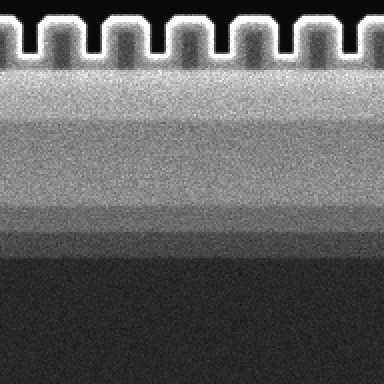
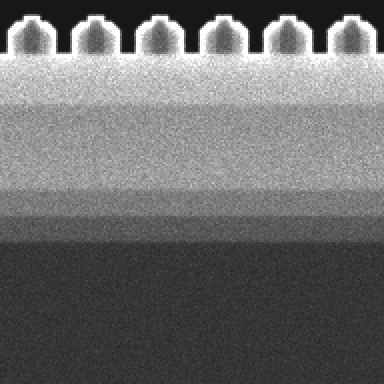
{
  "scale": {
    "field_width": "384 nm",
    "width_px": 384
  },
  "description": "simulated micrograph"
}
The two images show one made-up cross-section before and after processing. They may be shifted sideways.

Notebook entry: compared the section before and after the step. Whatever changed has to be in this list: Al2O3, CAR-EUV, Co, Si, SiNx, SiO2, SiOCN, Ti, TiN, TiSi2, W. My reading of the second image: Al2O3 removed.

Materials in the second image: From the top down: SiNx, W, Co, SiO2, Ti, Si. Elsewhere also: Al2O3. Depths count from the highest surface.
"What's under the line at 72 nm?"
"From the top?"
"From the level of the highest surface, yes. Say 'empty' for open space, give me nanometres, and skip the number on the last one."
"empty 14, Al2O3 24, W 50, Co 86, SiO2 26, Ti 26, Si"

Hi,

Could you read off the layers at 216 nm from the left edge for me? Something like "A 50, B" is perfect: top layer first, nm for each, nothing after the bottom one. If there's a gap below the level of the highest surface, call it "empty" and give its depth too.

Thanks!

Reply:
SiNx 38, W 50, Co 86, SiO2 26, Ti 26, Si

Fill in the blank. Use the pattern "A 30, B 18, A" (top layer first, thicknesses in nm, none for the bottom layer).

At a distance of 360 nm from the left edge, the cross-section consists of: empty 6, Al2O3 32, W 50, Co 86, SiO2 26, Ti 26, Si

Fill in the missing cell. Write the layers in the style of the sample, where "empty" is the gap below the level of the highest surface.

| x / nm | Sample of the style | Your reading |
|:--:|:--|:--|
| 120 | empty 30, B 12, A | empty 38, W 50, Co 86, SiO2 26, Ti 26, Si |